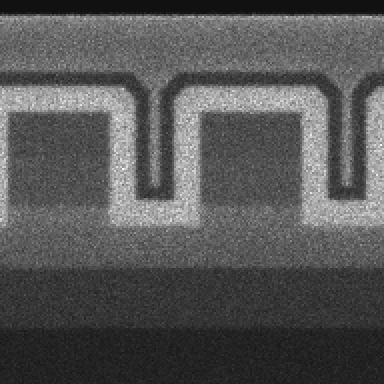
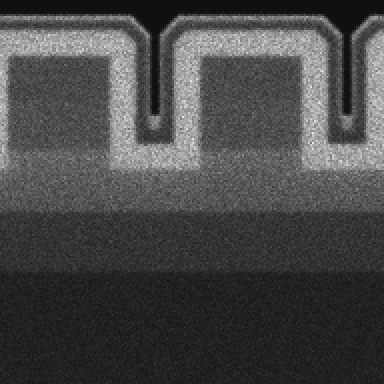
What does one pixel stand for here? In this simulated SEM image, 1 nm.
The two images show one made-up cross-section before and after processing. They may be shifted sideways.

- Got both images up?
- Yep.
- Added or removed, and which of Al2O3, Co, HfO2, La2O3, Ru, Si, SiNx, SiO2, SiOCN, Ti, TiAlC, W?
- removed, W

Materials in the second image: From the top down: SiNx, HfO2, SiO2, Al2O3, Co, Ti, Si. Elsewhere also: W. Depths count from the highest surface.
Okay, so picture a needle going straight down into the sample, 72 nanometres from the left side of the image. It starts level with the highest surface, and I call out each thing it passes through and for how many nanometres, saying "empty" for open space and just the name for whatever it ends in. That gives SiNx 14, HfO2 26, SiO2 44, Al2O3 50, Co 62, Ti 60, Si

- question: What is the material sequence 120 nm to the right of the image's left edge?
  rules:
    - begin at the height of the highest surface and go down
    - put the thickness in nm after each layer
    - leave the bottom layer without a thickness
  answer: SiNx 14, HfO2 140, Co 42, Ti 60, Si